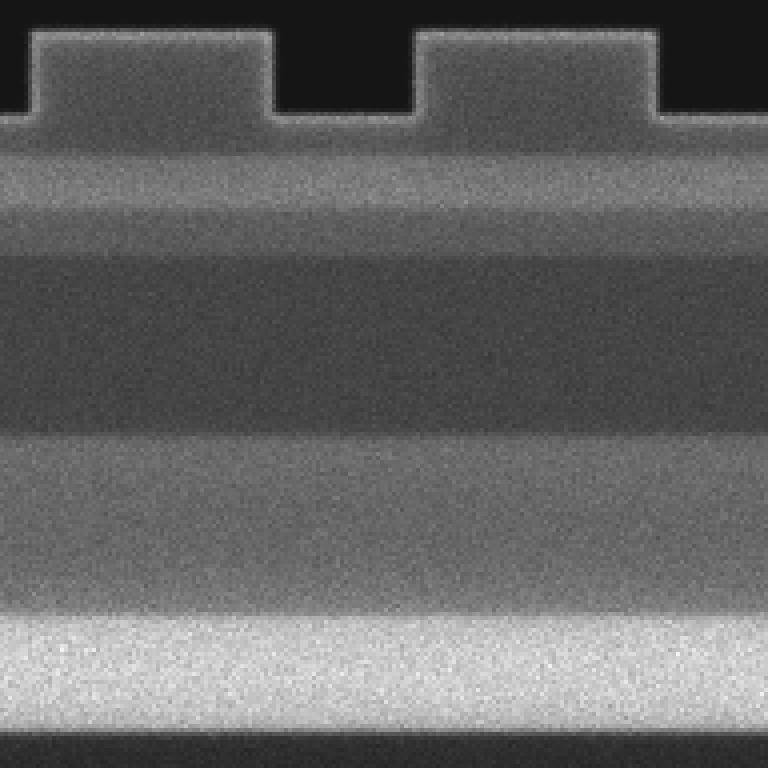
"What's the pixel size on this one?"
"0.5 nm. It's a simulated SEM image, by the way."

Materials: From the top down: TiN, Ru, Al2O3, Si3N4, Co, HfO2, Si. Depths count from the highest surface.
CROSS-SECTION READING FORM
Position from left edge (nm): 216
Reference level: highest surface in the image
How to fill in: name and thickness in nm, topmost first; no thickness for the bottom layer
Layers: TiN 62, Ru 26, Al2O3 24, Si3N4 90, Co 90, HfO2 58, Si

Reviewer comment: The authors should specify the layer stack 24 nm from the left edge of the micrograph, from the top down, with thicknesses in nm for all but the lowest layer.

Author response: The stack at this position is TiN 62, Ru 26, Al2O3 24, Si3N4 90, Co 90, HfO2 58, Si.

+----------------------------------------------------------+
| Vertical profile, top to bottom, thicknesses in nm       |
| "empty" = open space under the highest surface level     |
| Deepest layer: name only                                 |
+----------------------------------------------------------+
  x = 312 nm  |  TiN 62, Ru 26, Al2O3 24, Si3N4 90, Co 90, HfO2 58, Si